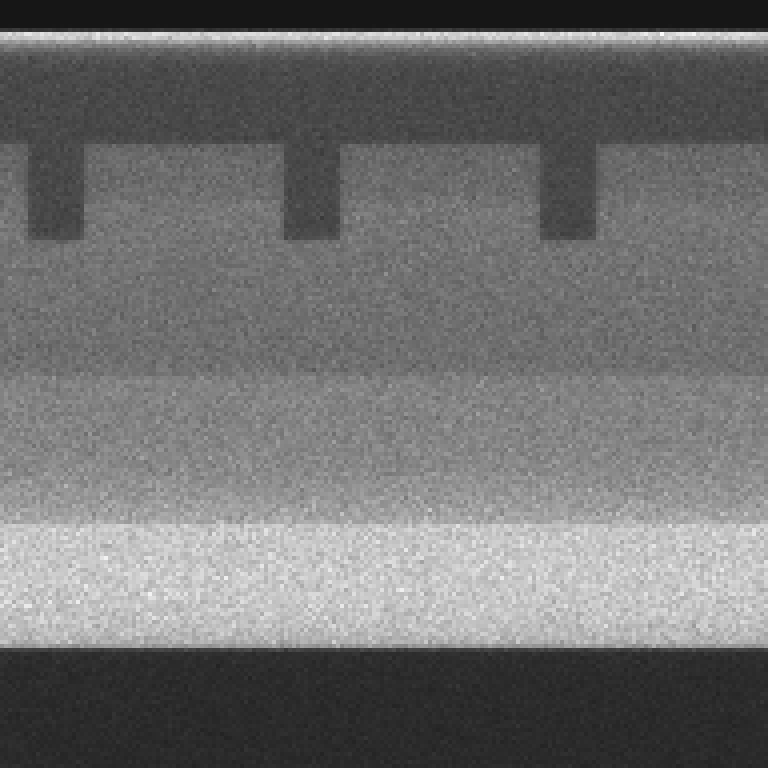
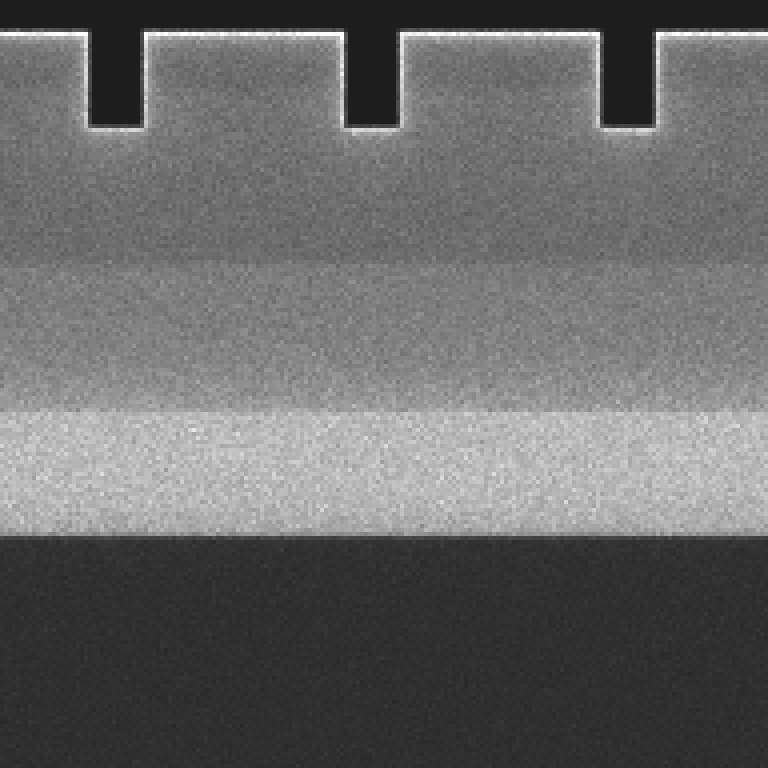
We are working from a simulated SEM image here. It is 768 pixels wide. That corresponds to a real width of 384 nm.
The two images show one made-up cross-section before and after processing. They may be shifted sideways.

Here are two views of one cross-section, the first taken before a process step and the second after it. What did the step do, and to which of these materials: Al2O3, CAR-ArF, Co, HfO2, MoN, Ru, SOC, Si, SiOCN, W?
It removed SOC.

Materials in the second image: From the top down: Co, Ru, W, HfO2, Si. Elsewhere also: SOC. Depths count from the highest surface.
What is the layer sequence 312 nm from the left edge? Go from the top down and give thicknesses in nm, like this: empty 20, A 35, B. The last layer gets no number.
empty 48, Ru 68, W 74, HfO2 62, Si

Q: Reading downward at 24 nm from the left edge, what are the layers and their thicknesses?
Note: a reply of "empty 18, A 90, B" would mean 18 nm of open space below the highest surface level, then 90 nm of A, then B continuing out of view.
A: Co 28, Ru 88, W 74, HfO2 62, Si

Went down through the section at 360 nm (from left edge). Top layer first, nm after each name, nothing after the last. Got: Co 28, Ru 88, W 74, HfO2 62, Si